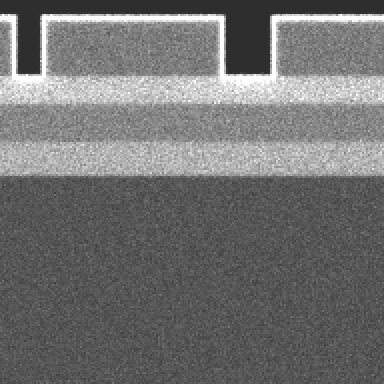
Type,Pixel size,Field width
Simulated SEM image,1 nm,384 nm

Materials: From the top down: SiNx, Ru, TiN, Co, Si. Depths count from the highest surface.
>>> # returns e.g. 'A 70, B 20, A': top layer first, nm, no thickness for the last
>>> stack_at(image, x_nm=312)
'SiNx 60, Ru 28, TiN 38, Co 34, Si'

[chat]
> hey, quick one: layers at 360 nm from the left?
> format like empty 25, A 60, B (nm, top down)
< SiNx 60, Ru 28, TiN 38, Co 34, Si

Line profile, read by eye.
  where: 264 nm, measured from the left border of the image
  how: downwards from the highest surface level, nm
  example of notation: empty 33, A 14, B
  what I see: empty 60, Ru 28, TiN 38, Co 34, Si